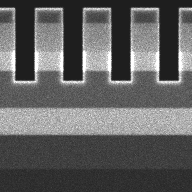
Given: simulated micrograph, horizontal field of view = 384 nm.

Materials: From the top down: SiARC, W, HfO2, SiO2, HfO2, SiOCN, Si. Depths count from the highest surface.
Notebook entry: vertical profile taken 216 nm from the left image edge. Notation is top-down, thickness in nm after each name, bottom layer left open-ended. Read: SiARC 30, W 58, HfO2 38, SiO2 74, HfO2 54, SiOCN 68, Si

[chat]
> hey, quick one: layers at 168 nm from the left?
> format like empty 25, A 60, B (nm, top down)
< SiARC 30, W 58, HfO2 38, SiO2 74, HfO2 54, SiOCN 68, Si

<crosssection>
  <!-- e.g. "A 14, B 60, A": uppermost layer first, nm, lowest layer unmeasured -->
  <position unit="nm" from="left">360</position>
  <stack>SiARC 30, W 58, HfO2 38, SiO2 74, HfO2 54, SiOCN 68, Si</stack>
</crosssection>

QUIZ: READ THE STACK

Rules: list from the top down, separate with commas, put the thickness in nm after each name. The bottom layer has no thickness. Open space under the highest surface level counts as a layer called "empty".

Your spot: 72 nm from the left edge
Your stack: SiARC 30, W 58, HfO2 38, SiO2 74, HfO2 54, SiOCN 68, Si